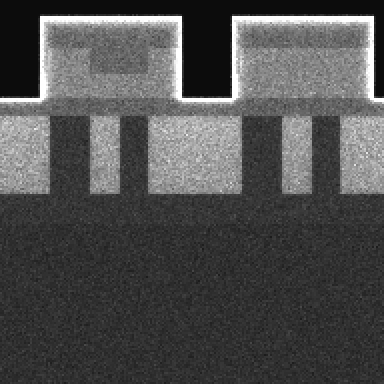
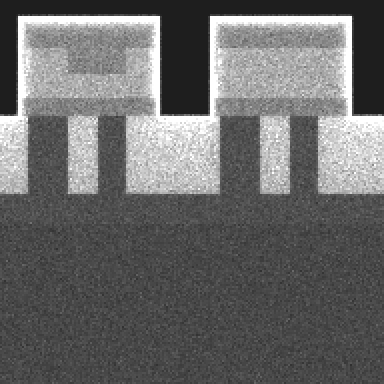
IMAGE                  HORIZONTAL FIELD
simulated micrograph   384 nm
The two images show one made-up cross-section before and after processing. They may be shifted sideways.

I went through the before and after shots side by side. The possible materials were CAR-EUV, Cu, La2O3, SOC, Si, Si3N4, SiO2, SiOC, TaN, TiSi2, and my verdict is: removed, Si3N4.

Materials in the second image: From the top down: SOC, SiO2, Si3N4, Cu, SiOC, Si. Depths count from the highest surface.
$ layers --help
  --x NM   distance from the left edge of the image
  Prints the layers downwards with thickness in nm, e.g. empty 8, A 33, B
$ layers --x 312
SOC 32, SiO2 50, Si3N4 18, SiOC 108, Si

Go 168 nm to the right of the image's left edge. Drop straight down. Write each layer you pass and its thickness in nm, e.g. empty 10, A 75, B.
empty 100, Cu 78, SiOC 30, Si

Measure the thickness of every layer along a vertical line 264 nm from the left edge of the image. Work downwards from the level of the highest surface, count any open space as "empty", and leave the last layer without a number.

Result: SOC 32, SiO2 50, Si3N4 18, Cu 78, SiOC 30, Si